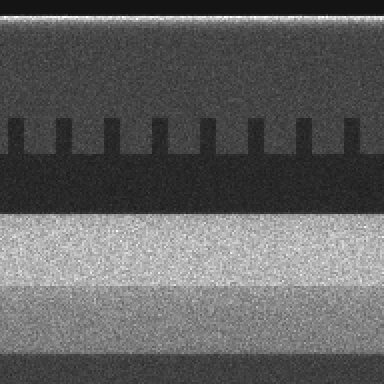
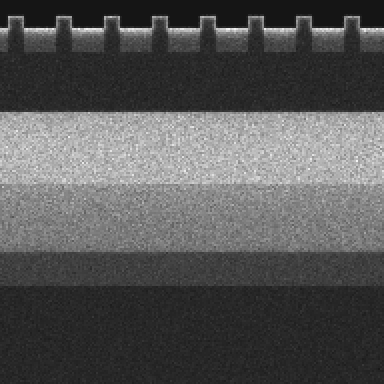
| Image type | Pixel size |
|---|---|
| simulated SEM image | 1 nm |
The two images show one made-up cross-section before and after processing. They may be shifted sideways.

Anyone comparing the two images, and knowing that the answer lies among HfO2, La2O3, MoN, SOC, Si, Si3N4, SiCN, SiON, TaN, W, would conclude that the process removed SOC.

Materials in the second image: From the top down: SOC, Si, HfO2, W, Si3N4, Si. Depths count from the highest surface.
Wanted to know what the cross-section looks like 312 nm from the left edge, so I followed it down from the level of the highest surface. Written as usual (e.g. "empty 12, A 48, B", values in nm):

empty 12, SOC 24, Si 60, HfO2 72, W 68, Si3N4 34, Si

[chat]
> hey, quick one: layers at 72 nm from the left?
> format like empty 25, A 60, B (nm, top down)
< empty 12, SOC 24, Si 60, HfO2 72, W 68, Si3N4 34, Si